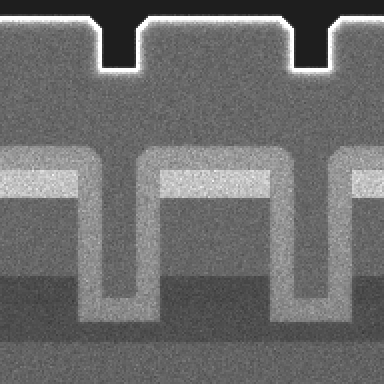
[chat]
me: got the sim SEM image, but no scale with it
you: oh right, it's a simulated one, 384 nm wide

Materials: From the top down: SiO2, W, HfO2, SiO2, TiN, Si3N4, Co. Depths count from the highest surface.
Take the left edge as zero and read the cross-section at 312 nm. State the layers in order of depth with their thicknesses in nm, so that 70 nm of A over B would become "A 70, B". empty 52, SiO2 230, W 24, Si3N4 20, Co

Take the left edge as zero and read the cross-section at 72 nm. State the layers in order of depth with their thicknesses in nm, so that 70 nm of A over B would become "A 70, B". SiO2 130, W 24, HfO2 28, SiO2 78, TiN 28, Si3N4 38, Co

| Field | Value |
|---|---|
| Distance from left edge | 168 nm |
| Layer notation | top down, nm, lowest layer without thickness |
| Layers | SiO2 130, W 24, HfO2 28, SiO2 78, TiN 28, Si3N4 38, Co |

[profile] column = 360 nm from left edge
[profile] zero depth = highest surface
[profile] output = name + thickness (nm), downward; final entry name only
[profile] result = SiO2 130, W 24, HfO2 28, SiO2 78, TiN 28, Si3N4 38, Co